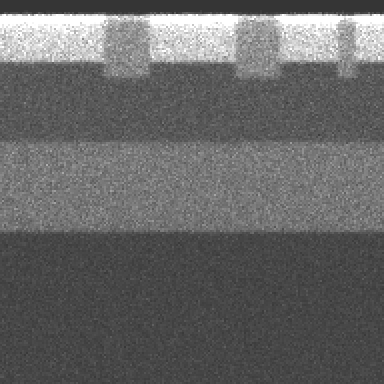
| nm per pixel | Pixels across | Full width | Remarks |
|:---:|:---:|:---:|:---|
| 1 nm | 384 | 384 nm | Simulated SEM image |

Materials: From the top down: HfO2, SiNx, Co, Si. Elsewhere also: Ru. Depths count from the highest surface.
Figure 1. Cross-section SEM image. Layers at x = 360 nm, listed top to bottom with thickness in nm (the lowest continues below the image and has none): HfO2 46, SiNx 80, Co 90, Si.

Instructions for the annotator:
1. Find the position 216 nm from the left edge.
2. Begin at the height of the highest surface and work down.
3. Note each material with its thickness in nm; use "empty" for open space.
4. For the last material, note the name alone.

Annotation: HfO2 46, SiNx 80, Co 90, Si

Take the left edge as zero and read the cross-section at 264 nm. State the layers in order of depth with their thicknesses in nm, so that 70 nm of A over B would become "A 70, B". Ru 62, SiNx 64, Co 90, Si